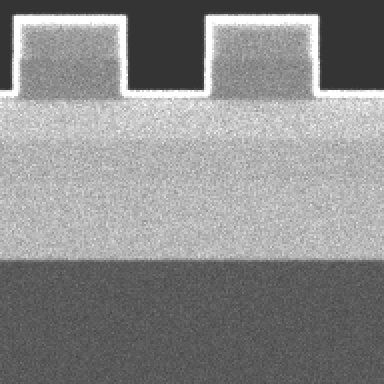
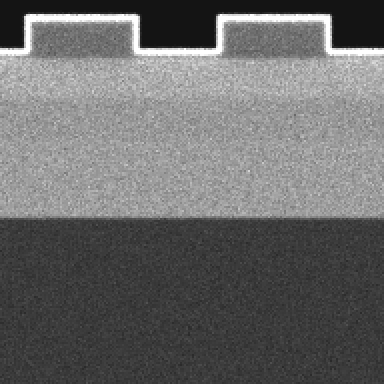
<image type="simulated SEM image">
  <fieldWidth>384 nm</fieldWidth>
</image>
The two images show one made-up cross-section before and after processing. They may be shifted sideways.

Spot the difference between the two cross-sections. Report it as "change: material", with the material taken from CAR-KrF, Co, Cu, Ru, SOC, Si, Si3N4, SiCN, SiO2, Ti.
removed: SOC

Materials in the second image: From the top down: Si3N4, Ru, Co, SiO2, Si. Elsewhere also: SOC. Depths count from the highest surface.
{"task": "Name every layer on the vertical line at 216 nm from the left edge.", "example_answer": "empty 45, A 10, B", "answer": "empty 34, Si3N4 8, Ru 40, Co 42, SiO2 78, Si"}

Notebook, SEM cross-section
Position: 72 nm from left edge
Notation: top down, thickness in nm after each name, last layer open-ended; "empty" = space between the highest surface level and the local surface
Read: Si3N4 42, Ru 40, Co 42, SiO2 78, Si